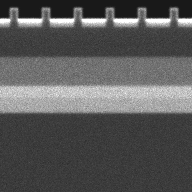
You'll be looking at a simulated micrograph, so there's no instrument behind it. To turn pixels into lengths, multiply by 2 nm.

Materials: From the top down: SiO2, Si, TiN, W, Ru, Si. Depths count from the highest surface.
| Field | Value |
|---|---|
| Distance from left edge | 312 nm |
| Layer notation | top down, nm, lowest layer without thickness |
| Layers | empty 22, SiO2 16, Si 60, TiN 58, W 24, Ru 30, Si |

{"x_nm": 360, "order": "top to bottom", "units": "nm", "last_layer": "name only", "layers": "empty 22, SiO2 16, Si 60, TiN 58, W 24, Ru 30, Si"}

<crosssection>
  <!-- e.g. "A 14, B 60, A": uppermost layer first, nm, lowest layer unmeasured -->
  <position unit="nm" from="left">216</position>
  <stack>Si 98, TiN 58, W 24, Ru 30, Si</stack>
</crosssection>